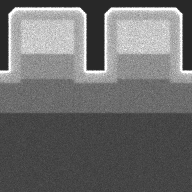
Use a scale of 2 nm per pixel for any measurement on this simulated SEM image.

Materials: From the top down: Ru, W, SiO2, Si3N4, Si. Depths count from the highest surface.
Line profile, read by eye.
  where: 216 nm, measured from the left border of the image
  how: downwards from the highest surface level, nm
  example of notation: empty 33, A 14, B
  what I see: empty 6, Ru 144, Si3N4 60, Si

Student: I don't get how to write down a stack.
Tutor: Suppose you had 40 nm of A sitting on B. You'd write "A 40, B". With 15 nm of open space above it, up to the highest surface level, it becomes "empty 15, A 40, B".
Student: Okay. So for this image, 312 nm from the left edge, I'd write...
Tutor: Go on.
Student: Ru 24, W 68, SiO2 50, Si3N4 68, Si